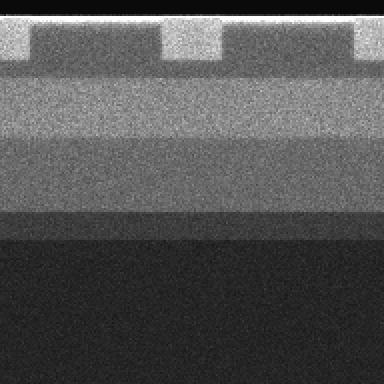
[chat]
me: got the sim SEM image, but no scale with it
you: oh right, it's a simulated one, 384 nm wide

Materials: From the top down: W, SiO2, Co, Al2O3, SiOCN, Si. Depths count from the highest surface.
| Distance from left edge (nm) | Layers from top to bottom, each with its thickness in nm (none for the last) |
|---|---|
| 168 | W 44, SiO2 18, Co 60, Al2O3 74, SiOCN 28, Si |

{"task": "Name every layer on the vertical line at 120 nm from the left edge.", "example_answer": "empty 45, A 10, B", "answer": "SiO2 62, Co 60, Al2O3 74, SiOCN 28, Si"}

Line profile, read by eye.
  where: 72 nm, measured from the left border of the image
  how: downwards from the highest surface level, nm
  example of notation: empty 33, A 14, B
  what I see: SiO2 62, Co 60, Al2O3 74, SiOCN 28, Si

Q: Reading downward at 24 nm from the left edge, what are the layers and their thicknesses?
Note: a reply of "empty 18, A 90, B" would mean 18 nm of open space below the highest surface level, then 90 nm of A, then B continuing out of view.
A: W 44, SiO2 18, Co 60, Al2O3 74, SiOCN 28, Si